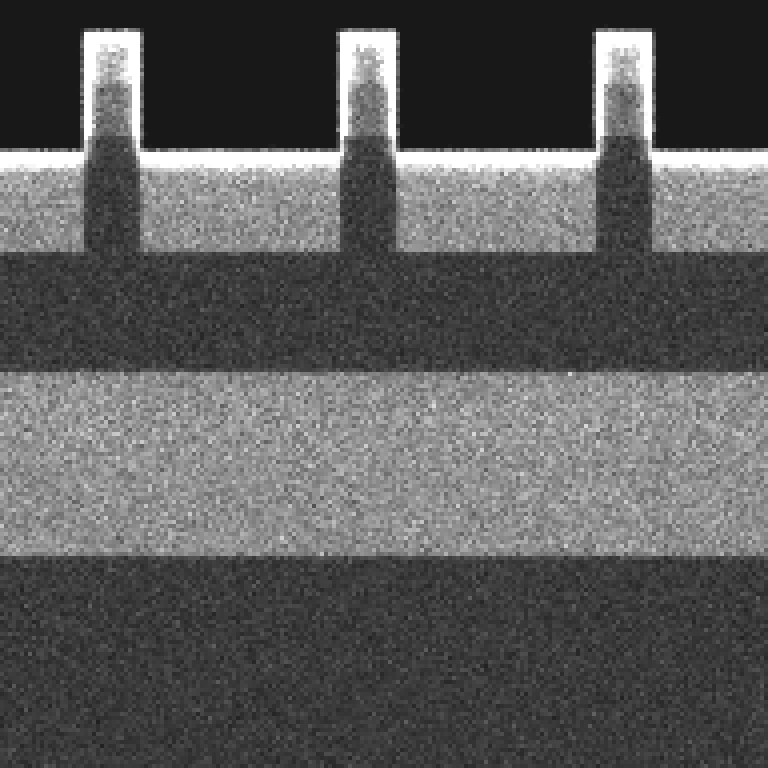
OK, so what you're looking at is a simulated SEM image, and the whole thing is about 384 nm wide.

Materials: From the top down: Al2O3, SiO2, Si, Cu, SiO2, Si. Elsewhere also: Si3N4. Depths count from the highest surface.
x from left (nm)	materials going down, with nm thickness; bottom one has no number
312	Al2O3 26, Si3N4 26, Si 118, Cu 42, SiO2 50, Si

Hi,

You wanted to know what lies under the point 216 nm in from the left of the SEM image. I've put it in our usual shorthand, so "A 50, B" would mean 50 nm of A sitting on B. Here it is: empty 60, Al2O3 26, SiO2 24, Si 60, Cu 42, SiO2 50, Si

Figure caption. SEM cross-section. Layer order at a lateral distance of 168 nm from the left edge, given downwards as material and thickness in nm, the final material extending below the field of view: empty 60, Al2O3 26, SiO2 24, Si 60, Cu 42, SiO2 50, Si